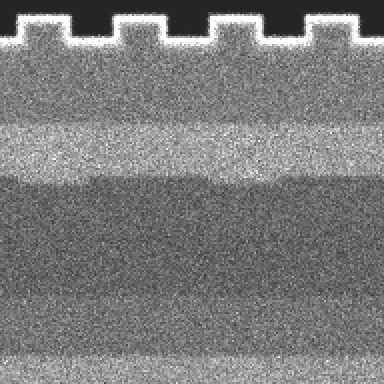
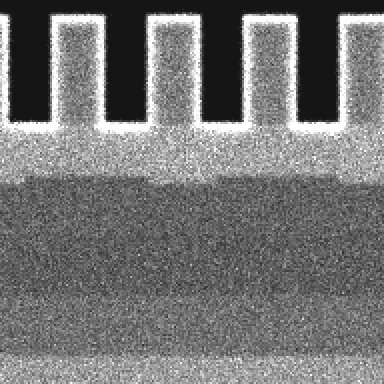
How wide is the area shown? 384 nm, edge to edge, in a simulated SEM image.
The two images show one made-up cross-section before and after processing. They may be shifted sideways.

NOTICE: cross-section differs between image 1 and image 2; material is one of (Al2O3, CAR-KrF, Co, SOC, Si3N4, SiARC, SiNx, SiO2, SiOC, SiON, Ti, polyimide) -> removed: SOC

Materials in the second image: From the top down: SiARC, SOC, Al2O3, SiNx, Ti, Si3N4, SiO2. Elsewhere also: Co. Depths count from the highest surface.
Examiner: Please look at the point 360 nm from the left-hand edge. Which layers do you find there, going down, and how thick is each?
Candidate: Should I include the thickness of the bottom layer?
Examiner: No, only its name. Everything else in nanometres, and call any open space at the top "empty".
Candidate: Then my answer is SiARC 22, SOC 86, Co 60, SiNx 52, Ti 60, Si3N4 60, SiO2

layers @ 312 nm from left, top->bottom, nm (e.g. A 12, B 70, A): empty 108, Al2O3 52, SiNx 60, Ti 60, Si3N4 60, SiO2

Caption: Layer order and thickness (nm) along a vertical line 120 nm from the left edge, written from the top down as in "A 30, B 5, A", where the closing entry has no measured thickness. empty 108, Al2O3 52, SiNx 60, Ti 60, Si3N4 60, SiO2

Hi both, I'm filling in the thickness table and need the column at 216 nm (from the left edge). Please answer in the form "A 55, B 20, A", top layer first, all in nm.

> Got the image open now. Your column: empty 108, Co 60, SiNx 52, Ti 60, Si3N4 60, SiO2